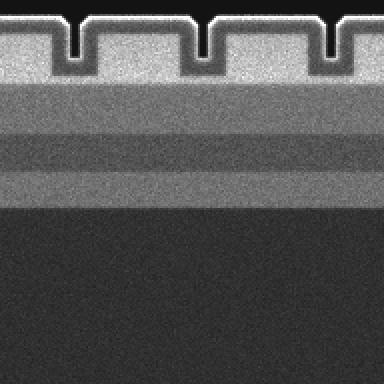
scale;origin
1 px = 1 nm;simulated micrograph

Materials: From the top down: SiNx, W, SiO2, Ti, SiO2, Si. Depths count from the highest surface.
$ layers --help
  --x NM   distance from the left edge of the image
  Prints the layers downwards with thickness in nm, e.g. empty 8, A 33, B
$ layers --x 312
SiNx 60, W 8, SiO2 50, Ti 38, SiO2 36, Si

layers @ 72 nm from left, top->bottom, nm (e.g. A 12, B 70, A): empty 42, SiNx 18, W 8, SiO2 50, Ti 38, SiO2 36, Si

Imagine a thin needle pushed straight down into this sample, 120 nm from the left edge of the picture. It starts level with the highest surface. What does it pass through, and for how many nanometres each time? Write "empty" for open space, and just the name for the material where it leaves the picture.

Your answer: SiNx 18, W 50, SiO2 50, Ti 38, SiO2 36, Si